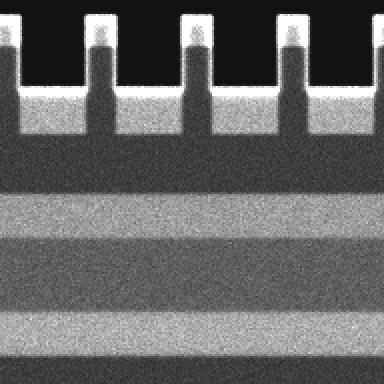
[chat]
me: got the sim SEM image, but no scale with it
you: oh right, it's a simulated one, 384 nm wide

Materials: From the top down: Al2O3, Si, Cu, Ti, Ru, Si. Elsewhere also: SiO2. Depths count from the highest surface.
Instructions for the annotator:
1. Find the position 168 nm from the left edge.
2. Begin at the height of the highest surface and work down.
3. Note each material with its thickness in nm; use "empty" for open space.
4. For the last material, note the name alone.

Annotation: empty 72, Al2O3 46, Si 60, Cu 44, Ti 74, Ru 44, Si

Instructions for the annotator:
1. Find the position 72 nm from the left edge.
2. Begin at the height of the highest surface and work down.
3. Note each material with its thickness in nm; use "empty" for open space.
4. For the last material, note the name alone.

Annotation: empty 72, Al2O3 46, Si 60, Cu 44, Ti 74, Ru 44, Si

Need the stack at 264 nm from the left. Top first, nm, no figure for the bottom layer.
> empty 72, Al2O3 46, Si 60, Cu 44, Ti 74, Ru 44, Si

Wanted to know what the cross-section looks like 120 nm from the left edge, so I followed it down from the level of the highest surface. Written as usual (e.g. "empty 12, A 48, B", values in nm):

empty 72, Al2O3 46, Si 60, Cu 44, Ti 74, Ru 44, Si